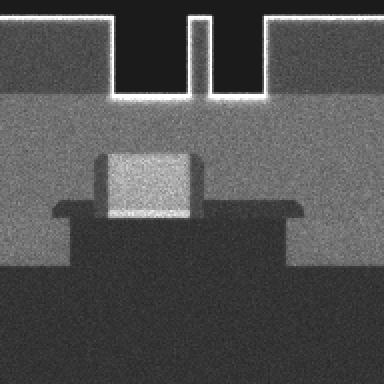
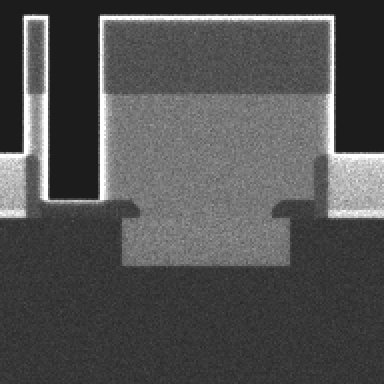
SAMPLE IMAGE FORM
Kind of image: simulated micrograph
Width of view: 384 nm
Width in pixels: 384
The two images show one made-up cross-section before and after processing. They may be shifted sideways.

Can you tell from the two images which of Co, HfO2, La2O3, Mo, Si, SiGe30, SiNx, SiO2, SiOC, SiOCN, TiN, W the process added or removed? Yes, it removed SiO2.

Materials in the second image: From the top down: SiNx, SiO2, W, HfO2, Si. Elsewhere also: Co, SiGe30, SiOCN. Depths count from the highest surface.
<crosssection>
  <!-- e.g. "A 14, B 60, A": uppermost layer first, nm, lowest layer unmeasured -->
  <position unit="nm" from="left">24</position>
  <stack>SiNx 78, SiO2 60, W 56, HfO2 8, Si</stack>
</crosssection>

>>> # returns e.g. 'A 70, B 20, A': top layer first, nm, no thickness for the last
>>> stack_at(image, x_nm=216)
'SiNx 78, SiO2 124, Co 48, Si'